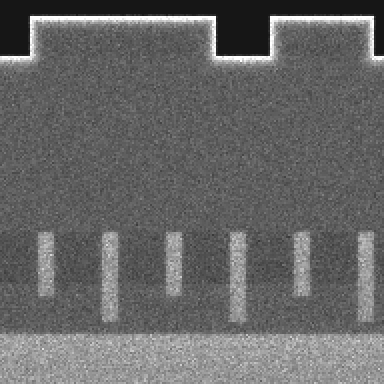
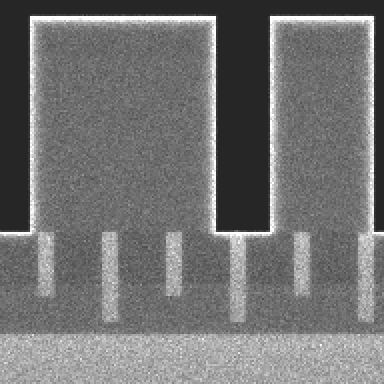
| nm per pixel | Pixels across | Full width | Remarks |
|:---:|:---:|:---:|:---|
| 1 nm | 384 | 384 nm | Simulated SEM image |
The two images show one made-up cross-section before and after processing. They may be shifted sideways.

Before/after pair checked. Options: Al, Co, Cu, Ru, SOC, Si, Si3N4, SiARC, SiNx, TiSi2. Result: removed SOC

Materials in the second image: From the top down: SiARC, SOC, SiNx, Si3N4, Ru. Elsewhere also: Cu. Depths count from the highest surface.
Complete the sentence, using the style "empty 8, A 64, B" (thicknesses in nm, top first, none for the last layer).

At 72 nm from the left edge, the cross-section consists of SiARC 40, SOC 176, SiNx 52, Si3N4 50, Ru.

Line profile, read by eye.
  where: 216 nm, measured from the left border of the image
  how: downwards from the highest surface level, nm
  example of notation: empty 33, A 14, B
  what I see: empty 216, SiNx 52, Si3N4 50, Ru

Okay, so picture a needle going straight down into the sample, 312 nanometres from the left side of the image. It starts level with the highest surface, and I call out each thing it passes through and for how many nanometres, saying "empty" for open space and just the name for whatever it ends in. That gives SiARC 40, SOC 176, SiNx 52, Si3N4 50, Ru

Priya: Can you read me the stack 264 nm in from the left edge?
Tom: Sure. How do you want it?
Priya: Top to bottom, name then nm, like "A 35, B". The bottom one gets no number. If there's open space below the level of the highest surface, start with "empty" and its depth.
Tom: empty 216, SiNx 52, Si3N4 50, Ru